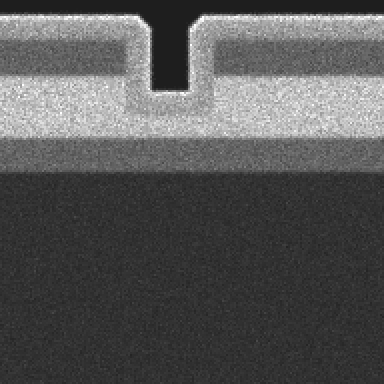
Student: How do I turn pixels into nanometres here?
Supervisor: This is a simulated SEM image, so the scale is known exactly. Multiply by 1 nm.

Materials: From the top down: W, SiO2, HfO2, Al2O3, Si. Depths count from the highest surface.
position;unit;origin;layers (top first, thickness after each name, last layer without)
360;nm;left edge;W 24, SiO2 36, HfO2 62, Al2O3 34, Si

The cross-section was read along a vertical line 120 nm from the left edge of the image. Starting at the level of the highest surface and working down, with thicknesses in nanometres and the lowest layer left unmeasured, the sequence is W 24, SiO2 36, HfO2 62, Al2O3 34, Si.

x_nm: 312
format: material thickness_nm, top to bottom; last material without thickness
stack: W 24, SiO2 36, HfO2 62, Al2O3 34, Si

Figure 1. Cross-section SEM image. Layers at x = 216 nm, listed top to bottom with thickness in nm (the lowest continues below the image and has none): W 24, SiO2 36, HfO2 62, Al2O3 34, Si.